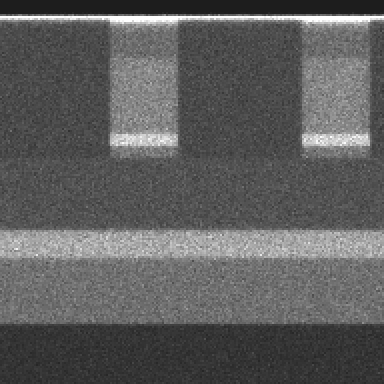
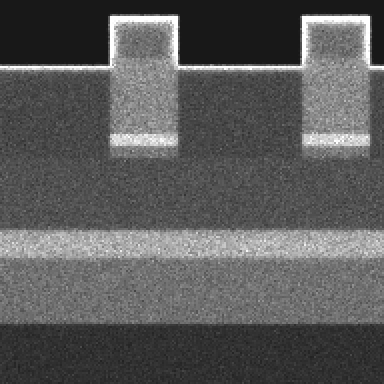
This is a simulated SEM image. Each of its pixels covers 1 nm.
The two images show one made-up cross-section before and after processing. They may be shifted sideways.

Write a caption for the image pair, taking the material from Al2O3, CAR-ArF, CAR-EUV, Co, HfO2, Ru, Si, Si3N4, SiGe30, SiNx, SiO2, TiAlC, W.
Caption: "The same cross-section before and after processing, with SiNx removed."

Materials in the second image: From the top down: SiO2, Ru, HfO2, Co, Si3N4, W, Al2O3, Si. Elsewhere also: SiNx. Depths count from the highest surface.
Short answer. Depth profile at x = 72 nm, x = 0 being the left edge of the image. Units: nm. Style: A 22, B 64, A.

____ empty 50, SiNx 92, Si3N4 72, W 28, Al2O3 66, Si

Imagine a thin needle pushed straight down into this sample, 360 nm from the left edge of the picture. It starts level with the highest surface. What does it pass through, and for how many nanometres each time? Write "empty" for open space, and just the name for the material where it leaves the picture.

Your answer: SiO2 42, Ru 76, HfO2 12, Co 12, Si3N4 72, W 28, Al2O3 66, Si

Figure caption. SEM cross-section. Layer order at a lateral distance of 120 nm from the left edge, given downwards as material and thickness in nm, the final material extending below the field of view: SiO2 42, Ru 76, HfO2 12, Co 12, Si3N4 72, W 28, Al2O3 66, Si